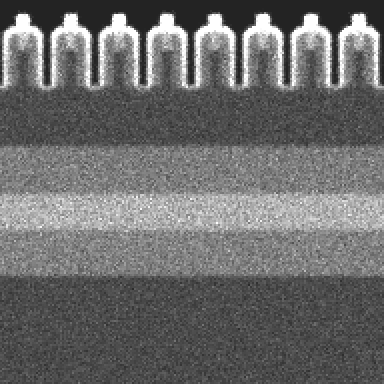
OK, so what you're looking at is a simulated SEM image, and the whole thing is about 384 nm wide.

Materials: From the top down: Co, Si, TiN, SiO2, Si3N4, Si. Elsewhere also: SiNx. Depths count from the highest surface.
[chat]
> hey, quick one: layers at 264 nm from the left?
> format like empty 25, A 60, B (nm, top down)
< Co 34, Si 96, TiN 48, SiO2 36, Si3N4 46, Si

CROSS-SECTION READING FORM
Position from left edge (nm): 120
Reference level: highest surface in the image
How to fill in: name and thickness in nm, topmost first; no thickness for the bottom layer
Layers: Co 34, Si 96, TiN 48, SiO2 36, Si3N4 46, Si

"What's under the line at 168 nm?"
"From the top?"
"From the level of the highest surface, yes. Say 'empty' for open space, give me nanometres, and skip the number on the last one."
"Co 34, Si 96, TiN 48, SiO2 36, Si3N4 46, Si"